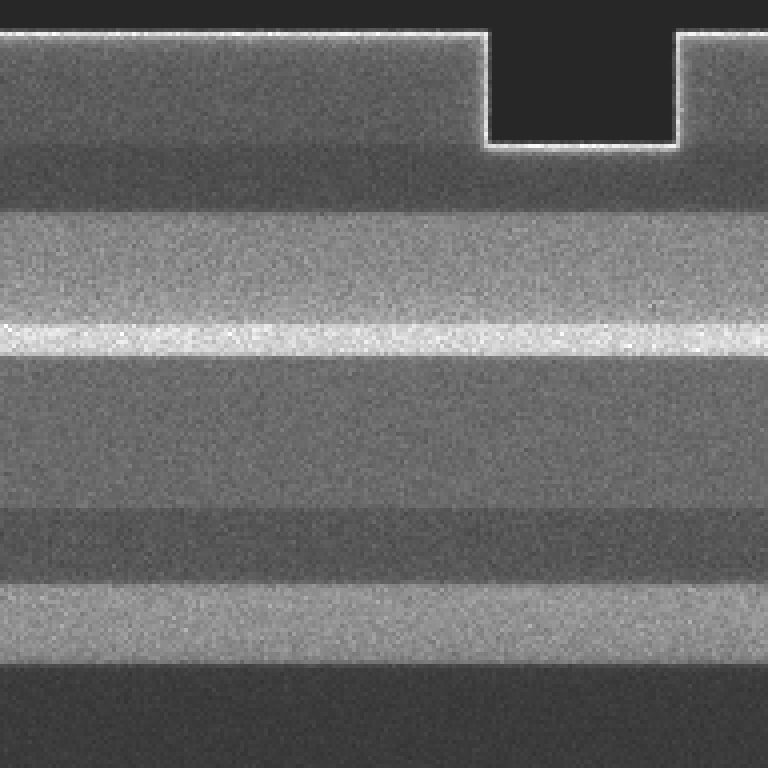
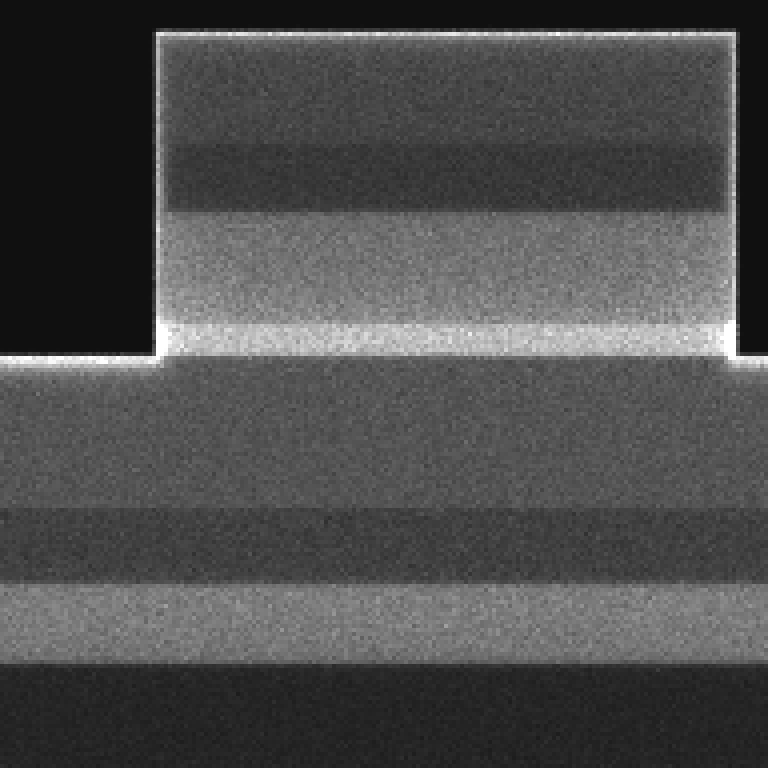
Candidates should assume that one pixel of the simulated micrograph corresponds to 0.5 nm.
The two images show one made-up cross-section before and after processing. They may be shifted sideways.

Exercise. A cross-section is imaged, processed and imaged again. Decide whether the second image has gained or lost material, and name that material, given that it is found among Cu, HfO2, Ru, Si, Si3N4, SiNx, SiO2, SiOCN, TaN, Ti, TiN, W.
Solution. removed: HfO2 and Ru and SiNx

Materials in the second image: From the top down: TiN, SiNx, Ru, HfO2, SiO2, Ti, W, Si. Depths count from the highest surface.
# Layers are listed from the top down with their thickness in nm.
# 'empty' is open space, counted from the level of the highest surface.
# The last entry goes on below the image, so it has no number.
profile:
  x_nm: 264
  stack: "TiN 56, SiNx 34, Ru 56, HfO2 16, SiO2 76, Ti 38, W 40, Si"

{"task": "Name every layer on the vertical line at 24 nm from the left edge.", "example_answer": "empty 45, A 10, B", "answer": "empty 162, SiO2 76, Ti 38, W 40, Si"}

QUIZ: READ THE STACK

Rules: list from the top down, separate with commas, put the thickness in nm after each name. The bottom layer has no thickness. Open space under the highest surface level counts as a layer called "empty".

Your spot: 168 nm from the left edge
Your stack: TiN 56, SiNx 34, Ru 56, HfO2 16, SiO2 76, Ti 38, W 40, Si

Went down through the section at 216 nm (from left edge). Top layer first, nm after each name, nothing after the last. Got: TiN 56, SiNx 34, Ru 56, HfO2 16, SiO2 76, Ti 38, W 40, Si